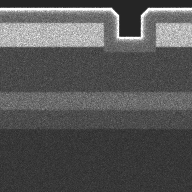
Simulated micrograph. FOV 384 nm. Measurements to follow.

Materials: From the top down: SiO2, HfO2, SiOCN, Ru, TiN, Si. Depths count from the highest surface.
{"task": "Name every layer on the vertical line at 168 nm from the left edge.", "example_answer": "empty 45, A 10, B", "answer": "SiO2 30, HfO2 48, SiOCN 90, Ru 36, TiN 38, Si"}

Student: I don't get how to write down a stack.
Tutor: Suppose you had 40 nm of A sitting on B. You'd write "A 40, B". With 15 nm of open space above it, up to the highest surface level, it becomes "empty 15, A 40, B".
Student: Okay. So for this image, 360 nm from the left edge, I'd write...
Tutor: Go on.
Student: SiO2 30, HfO2 48, SiOCN 90, Ru 36, TiN 38, Si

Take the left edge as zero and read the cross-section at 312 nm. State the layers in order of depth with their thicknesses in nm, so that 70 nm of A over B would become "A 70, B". SiO2 30, HfO2 48, SiOCN 90, Ru 36, TiN 38, Si